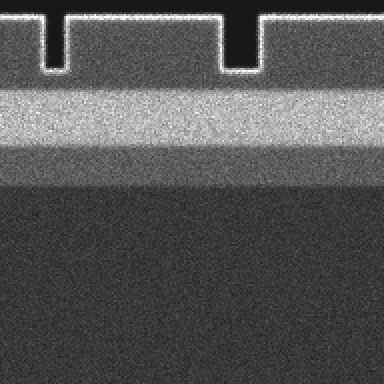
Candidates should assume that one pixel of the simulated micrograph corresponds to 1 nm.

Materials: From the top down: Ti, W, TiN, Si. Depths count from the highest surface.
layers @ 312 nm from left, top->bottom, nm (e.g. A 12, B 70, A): Ti 74, W 56, TiN 40, Si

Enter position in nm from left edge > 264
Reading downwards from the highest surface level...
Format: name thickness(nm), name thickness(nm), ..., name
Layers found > Ti 74, W 56, TiN 40, Si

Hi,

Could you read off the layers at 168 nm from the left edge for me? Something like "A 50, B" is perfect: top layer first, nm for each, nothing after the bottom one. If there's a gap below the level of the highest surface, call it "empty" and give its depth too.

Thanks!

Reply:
Ti 74, W 56, TiN 40, Si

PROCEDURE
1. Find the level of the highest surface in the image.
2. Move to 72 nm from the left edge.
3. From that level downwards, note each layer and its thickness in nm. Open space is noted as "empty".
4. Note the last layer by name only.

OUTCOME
Ti 74, W 56, TiN 40, Si